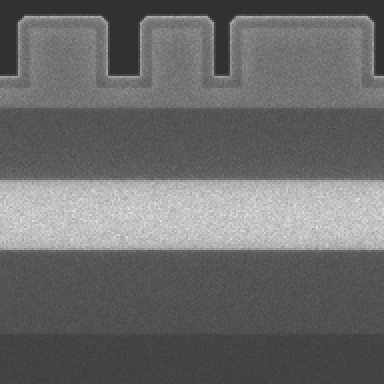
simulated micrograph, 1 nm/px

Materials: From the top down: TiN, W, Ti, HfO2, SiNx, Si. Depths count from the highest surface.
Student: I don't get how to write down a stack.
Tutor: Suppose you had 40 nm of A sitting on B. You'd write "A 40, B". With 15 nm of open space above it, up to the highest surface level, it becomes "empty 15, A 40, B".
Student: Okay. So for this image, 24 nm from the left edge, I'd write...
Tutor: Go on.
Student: TiN 72, W 20, Ti 72, HfO2 70, SiNx 84, Si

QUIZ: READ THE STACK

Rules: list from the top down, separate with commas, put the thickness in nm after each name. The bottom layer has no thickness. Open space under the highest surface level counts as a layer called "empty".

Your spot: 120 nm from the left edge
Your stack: empty 60, TiN 12, W 20, Ti 72, HfO2 70, SiNx 84, Si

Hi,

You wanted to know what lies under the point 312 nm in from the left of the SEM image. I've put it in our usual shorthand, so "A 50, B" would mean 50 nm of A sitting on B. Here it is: TiN 12, W 80, Ti 72, HfO2 70, SiNx 84, Si